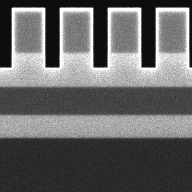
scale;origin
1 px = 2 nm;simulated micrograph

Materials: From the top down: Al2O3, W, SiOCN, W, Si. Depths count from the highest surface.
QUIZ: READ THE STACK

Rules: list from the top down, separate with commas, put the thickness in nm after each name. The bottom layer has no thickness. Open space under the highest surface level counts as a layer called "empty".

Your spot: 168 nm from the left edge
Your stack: Al2O3 90, W 68, SiOCN 56, W 46, Si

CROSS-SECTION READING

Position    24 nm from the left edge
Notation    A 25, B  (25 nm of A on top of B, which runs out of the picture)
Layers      Al2O3 90, W 68, SiOCN 56, W 46, Si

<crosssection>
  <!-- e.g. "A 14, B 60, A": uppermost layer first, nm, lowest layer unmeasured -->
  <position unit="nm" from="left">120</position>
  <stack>Al2O3 90, W 68, SiOCN 56, W 46, Si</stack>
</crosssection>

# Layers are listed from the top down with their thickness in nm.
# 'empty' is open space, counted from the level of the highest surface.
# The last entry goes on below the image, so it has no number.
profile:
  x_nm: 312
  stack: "Al2O3 90, W 68, SiOCN 56, W 46, Si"